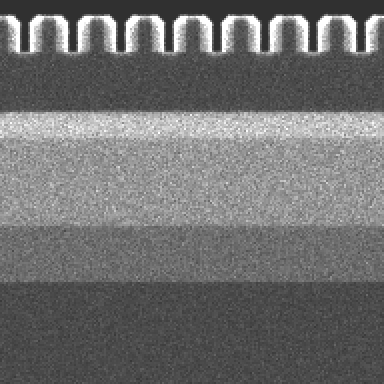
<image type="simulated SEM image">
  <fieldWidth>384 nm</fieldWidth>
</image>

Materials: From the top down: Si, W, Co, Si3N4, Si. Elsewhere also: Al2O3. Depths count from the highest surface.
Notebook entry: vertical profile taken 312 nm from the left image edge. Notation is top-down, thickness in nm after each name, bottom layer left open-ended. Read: empty 36, Si 60, W 26, Co 88, Si3N4 56, Si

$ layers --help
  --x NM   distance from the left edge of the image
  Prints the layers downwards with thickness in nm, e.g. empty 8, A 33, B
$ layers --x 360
empty 36, Si 60, W 26, Co 88, Si3N4 56, Si